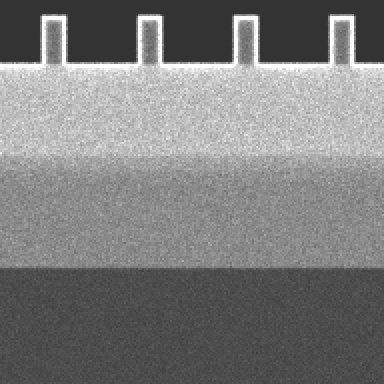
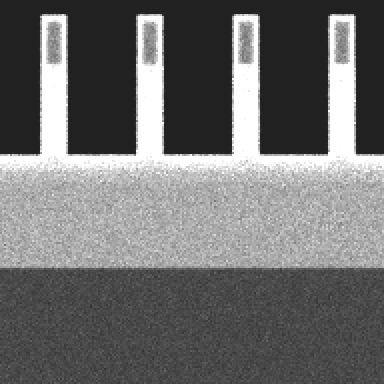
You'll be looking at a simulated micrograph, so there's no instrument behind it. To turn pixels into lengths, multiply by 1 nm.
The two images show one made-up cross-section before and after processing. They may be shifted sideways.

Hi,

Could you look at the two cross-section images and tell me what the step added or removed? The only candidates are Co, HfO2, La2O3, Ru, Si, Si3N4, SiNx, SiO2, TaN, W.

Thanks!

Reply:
removed W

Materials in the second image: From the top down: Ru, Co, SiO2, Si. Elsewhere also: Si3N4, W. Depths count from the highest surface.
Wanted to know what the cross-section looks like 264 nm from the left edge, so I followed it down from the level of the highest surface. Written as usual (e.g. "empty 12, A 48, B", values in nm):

empty 140, Ru 14, Co 12, SiO2 86, Si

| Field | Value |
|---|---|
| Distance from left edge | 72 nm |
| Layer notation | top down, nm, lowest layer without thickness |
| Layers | empty 140, Ru 14, Co 12, SiO2 86, Si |